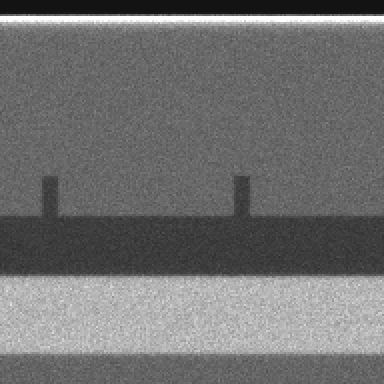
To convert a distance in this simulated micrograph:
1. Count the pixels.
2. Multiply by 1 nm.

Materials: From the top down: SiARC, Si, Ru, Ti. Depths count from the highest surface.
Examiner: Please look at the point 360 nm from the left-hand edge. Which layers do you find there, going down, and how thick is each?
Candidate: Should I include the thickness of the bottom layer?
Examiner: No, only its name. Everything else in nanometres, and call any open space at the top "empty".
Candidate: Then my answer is SiARC 200, Si 60, Ru 78, Ti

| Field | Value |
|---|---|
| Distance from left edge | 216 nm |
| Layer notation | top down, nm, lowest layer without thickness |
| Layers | SiARC 200, Si 60, Ru 78, Ti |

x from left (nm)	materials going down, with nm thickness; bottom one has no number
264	SiARC 200, Si 60, Ru 78, Ti